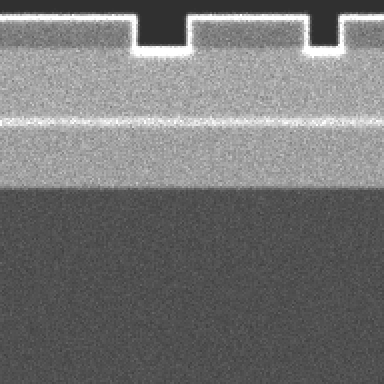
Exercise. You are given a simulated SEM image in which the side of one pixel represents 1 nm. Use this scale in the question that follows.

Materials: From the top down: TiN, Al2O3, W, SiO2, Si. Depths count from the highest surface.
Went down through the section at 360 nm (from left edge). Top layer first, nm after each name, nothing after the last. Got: TiN 32, Al2O3 70, W 8, SiO2 62, Si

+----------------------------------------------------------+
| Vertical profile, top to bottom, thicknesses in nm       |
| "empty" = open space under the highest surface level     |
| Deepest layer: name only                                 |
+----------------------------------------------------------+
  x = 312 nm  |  empty 32, Al2O3 70, W 8, SiO2 62, Si